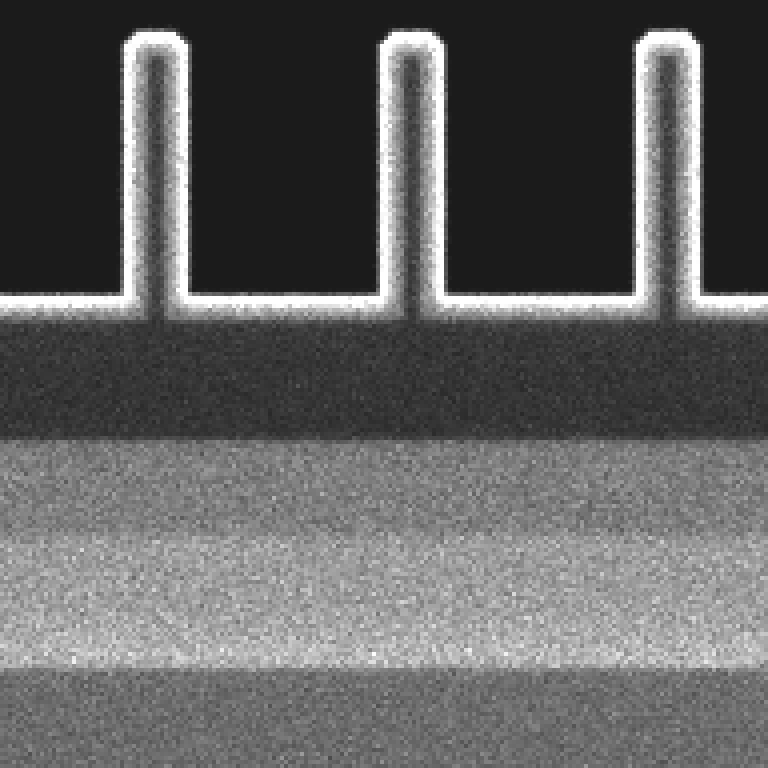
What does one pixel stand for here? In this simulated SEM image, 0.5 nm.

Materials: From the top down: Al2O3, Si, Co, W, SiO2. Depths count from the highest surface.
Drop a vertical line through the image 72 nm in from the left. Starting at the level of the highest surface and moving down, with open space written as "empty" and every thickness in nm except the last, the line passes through Al2O3 144, Si 60, Co 48, W 66, SiO2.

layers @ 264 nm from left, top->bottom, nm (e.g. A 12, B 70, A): empty 132, Al2O3 12, Si 60, Co 48, W 66, SiO2